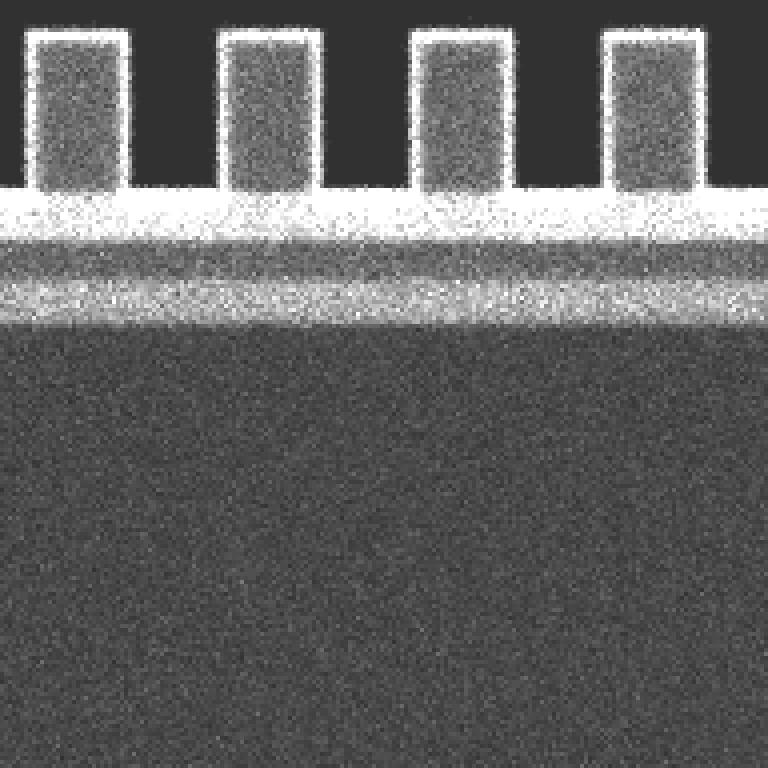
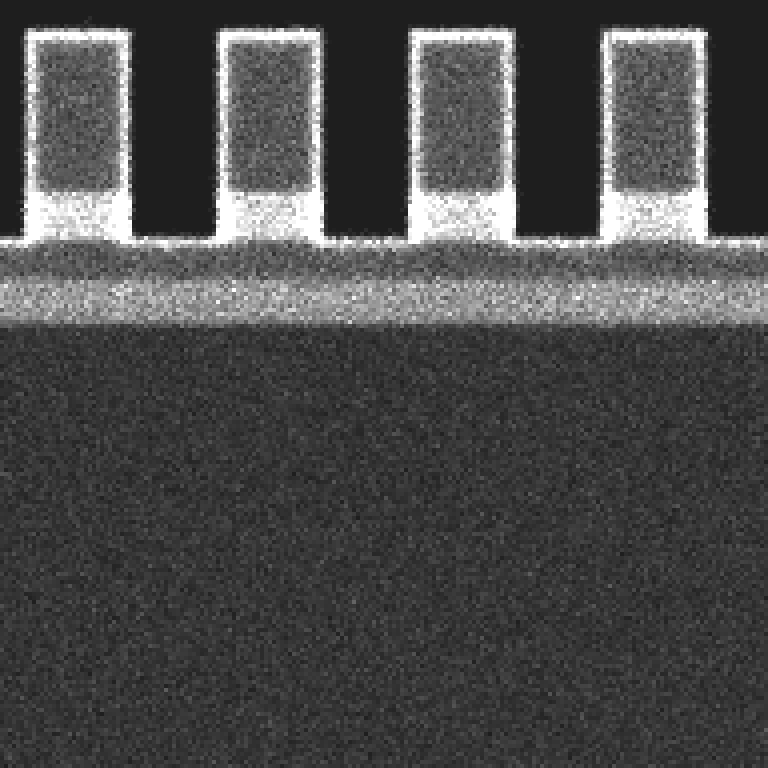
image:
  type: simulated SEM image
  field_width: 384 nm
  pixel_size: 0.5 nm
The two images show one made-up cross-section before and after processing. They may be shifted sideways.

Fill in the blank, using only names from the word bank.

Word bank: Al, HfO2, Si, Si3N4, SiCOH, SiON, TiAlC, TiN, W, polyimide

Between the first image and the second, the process removed HfO2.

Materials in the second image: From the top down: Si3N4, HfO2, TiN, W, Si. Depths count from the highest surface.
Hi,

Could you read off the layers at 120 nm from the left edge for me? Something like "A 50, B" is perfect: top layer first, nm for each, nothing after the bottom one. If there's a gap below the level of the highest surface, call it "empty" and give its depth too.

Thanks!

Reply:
Si3N4 80, HfO2 24, TiN 20, W 22, Si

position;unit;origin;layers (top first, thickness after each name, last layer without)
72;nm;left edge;empty 104, TiN 20, W 22, Si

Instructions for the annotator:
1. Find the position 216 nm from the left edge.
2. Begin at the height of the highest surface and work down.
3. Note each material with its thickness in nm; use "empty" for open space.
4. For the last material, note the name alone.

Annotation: Si3N4 80, HfO2 24, TiN 20, W 22, Si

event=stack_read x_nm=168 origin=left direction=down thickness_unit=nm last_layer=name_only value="empty 104, TiN 20, W 22, Si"